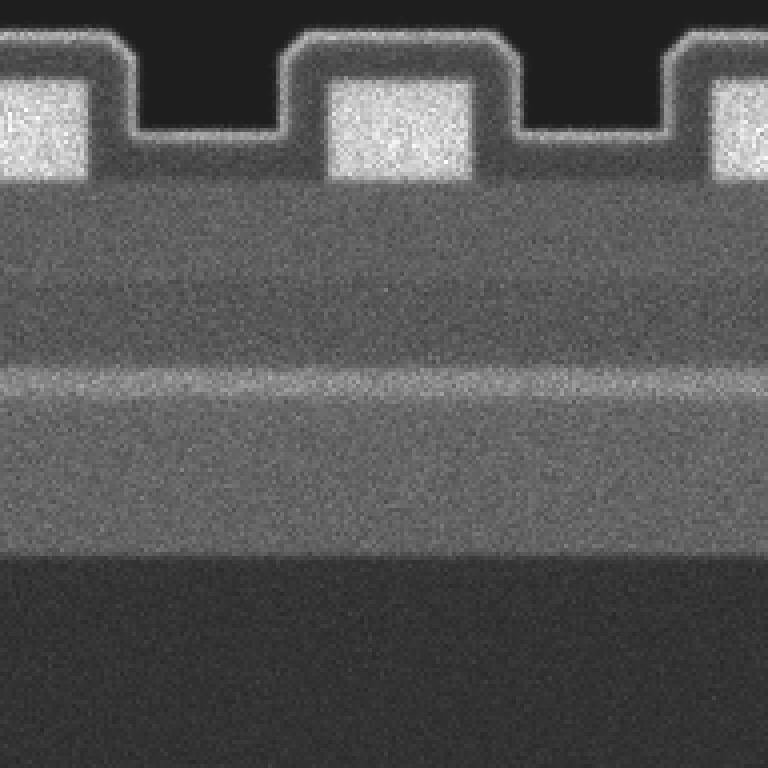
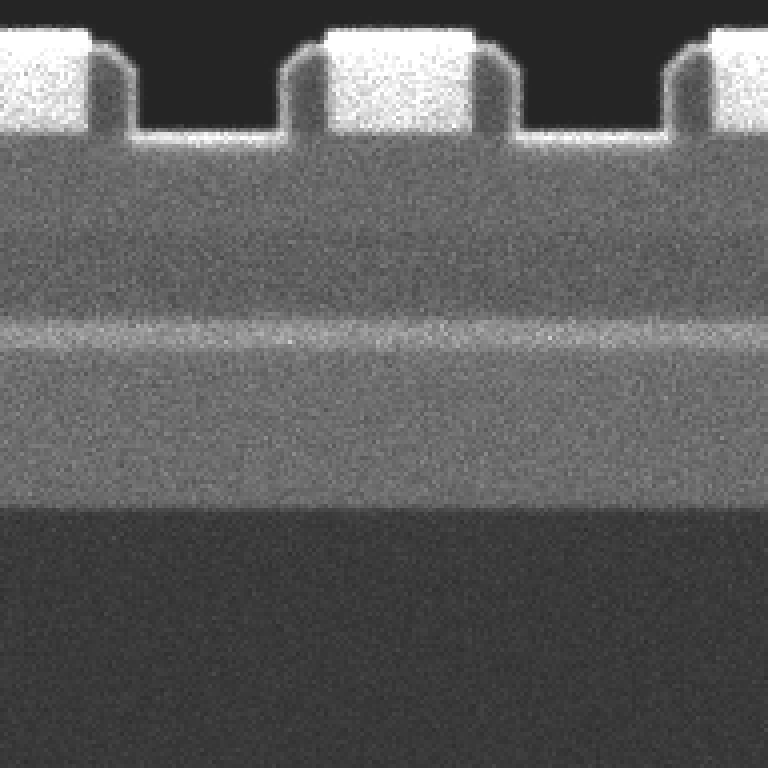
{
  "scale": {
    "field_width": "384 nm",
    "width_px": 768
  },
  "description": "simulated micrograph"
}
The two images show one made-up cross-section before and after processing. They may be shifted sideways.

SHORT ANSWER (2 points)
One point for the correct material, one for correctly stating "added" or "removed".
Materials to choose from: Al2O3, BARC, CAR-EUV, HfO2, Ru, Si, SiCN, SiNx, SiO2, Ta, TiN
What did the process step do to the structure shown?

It removed SiNx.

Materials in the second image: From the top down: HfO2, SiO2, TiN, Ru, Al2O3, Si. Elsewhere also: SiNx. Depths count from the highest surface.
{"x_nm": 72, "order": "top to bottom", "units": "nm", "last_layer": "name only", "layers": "empty 50, SiO2 50, TiN 44, Ru 14, Al2O3 80, Si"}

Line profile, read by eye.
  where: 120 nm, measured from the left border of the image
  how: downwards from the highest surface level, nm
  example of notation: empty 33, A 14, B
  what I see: empty 50, SiO2 50, TiN 44, Ru 14, Al2O3 80, Si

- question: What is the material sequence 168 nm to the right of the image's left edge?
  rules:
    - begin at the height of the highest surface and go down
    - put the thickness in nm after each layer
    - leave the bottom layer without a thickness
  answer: HfO2 50, SiO2 50, TiN 44, Ru 14, Al2O3 80, Si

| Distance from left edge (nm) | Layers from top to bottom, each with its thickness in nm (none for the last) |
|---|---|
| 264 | empty 50, SiO2 50, TiN 44, Ru 14, Al2O3 80, Si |